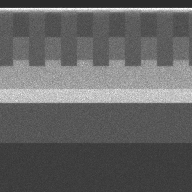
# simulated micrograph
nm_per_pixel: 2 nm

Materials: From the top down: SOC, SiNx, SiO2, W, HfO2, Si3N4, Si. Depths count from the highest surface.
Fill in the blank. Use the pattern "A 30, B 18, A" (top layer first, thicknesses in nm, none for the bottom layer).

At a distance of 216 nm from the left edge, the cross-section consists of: SOC 116, W 46, HfO2 28, Si3N4 80, Si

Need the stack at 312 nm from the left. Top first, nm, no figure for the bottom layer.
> SOC 6, SiNx 52, SiO2 46, W 58, HfO2 28, Si3N4 80, Si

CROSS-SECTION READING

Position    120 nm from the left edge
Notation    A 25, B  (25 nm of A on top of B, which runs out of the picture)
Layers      SOC 6, SiNx 52, SiO2 46, W 58, HfO2 28, Si3N4 80, Si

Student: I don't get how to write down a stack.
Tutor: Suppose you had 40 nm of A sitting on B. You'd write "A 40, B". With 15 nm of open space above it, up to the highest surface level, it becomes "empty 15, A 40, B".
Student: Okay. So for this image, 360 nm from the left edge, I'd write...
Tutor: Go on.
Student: SOC 6, SiNx 52, SiO2 46, W 58, HfO2 28, Si3N4 80, Si